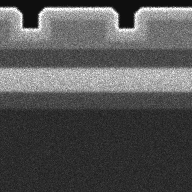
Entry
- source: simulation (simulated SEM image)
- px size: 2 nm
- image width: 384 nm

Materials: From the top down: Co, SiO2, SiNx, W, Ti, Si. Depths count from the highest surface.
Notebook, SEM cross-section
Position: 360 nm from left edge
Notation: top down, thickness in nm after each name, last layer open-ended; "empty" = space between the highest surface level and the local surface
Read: Co 24, SiO2 58, SiNx 38, W 48, Ti 34, Si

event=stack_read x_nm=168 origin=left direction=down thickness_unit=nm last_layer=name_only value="Co 24, SiO2 58, SiNx 38, W 48, Ti 34, Si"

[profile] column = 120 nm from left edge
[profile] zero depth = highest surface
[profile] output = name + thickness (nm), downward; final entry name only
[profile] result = Co 24, SiO2 58, SiNx 38, W 48, Ti 34, Si